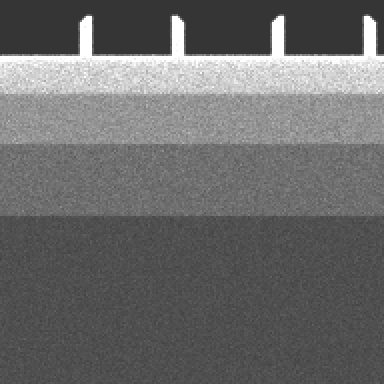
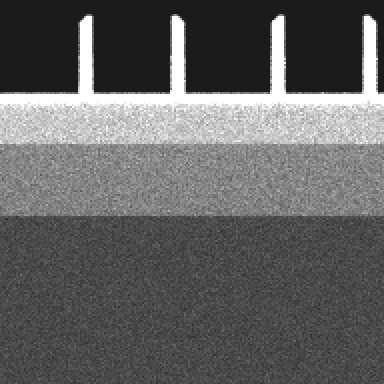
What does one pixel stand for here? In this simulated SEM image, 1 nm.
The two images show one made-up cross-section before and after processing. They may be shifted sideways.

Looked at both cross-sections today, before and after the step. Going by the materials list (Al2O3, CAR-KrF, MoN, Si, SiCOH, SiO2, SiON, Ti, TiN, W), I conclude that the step removed W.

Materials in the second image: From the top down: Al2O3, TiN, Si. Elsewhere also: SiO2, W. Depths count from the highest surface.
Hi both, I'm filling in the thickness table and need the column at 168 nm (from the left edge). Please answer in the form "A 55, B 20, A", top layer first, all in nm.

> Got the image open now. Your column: empty 78, Al2O3 50, TiN 72, Si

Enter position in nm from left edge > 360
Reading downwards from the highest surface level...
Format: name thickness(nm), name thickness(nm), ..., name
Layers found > empty 78, Al2O3 50, TiN 72, Si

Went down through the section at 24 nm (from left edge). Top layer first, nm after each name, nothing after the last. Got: empty 78, Al2O3 50, TiN 72, Si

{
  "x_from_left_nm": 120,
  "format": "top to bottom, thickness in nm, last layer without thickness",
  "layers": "empty 78, Al2O3 50, TiN 72, Si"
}